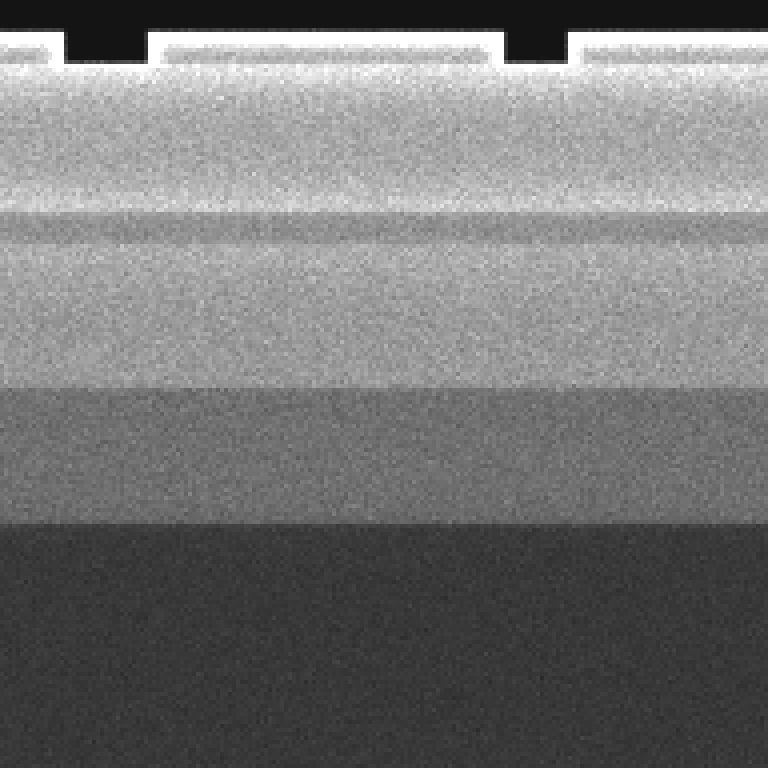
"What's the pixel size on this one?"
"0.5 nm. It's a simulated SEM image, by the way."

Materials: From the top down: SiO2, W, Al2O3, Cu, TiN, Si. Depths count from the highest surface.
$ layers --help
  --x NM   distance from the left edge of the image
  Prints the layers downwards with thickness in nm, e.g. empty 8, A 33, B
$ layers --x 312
SiO2 16, W 74, Al2O3 16, Cu 72, TiN 68, Si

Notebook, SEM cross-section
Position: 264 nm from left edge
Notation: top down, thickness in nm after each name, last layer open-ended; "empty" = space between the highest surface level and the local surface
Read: empty 16, W 74, Al2O3 16, Cu 72, TiN 68, Si